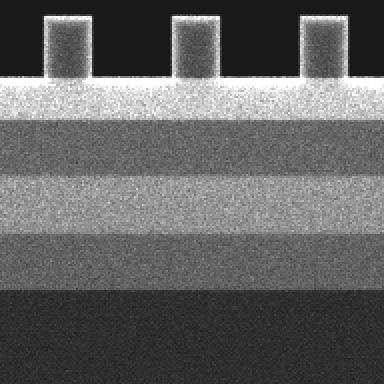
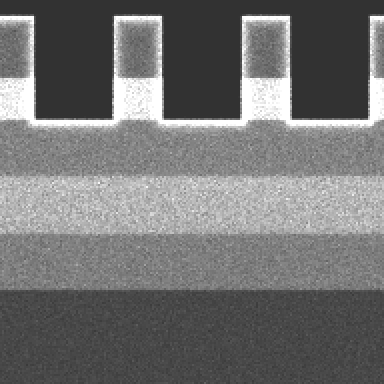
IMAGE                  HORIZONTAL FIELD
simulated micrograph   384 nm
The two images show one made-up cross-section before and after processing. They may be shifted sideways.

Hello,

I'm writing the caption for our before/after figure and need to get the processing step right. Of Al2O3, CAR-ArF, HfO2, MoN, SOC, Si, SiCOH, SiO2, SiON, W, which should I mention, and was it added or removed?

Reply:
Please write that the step removed HfO2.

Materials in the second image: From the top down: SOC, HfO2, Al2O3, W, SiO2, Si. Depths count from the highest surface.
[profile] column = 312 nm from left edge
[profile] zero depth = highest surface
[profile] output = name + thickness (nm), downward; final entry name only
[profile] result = empty 104, Al2O3 56, W 58, SiO2 56, Si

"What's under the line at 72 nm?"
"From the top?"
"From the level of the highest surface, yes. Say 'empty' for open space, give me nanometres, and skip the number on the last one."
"empty 104, Al2O3 56, W 58, SiO2 56, Si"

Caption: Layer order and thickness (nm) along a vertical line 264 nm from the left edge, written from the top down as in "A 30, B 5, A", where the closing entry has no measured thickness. SOC 62, HfO2 42, Al2O3 56, W 58, SiO2 56, Si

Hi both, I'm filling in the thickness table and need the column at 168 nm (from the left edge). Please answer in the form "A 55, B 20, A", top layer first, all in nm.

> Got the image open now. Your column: empty 104, Al2O3 56, W 58, SiO2 56, Si